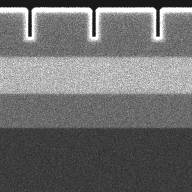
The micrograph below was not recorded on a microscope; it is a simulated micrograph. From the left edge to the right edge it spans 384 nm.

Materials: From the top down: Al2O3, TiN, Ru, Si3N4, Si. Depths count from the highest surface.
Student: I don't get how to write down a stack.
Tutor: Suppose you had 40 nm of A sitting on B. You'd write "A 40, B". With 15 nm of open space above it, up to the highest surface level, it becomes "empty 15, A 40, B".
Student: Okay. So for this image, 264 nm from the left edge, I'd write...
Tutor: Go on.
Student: Al2O3 10, TiN 88, Ru 74, Si3N4 68, Si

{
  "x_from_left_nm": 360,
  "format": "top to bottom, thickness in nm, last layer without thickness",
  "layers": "Al2O3 10, TiN 88, Ru 74, Si3N4 68, Si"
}